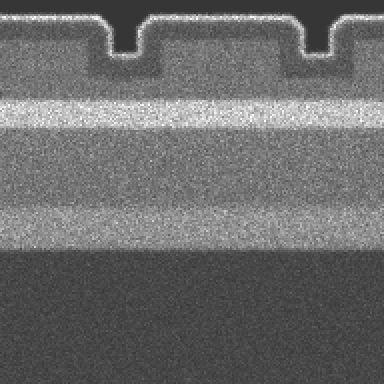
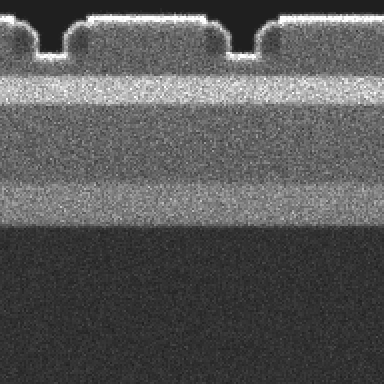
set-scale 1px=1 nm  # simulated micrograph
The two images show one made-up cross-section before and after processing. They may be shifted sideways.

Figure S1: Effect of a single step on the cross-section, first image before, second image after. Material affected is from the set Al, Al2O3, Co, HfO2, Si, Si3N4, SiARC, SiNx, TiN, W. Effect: removed SiNx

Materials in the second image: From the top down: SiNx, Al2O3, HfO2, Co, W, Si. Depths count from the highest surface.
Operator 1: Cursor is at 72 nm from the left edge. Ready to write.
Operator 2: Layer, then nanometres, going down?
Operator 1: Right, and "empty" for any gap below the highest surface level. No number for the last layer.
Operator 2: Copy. empty 10, SiNx 28, Al2O3 22, HfO2 28, Co 80, W 42, Si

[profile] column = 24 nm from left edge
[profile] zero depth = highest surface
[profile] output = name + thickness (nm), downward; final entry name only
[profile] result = empty 6, SiNx 32, Al2O3 22, HfO2 28, Co 80, W 42, Si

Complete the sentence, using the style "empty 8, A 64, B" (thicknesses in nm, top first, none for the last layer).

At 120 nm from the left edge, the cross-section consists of Al2O3 60, HfO2 28, Co 80, W 42, Si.